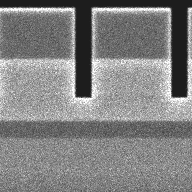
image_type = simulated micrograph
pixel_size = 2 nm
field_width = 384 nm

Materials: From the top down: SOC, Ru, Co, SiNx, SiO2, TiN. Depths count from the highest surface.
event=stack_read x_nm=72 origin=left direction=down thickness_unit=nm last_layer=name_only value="SOC 102, Ru 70, Co 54, SiNx 34, SiO2 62, TiN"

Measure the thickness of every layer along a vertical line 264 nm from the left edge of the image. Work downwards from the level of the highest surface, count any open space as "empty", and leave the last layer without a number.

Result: SOC 102, Ru 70, Co 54, SiNx 34, SiO2 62, TiN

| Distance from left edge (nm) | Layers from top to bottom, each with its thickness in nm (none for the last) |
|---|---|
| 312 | SOC 102, Ru 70, Co 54, SiNx 34, SiO2 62, TiN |